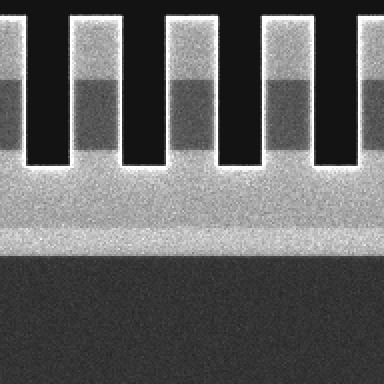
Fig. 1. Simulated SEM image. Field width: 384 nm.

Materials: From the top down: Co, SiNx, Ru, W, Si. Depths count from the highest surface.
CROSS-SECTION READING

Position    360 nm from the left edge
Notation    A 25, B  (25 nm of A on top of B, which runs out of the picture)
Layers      Co 64, SiNx 70, Ru 78, W 28, Si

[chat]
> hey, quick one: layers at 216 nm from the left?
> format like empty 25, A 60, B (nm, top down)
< Co 64, SiNx 70, Ru 78, W 28, Si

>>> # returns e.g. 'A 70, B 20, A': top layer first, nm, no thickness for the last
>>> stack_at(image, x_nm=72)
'Co 64, SiNx 70, Ru 78, W 28, Si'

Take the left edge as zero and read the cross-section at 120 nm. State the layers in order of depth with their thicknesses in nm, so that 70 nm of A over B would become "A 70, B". Co 64, SiNx 70, Ru 78, W 28, Si